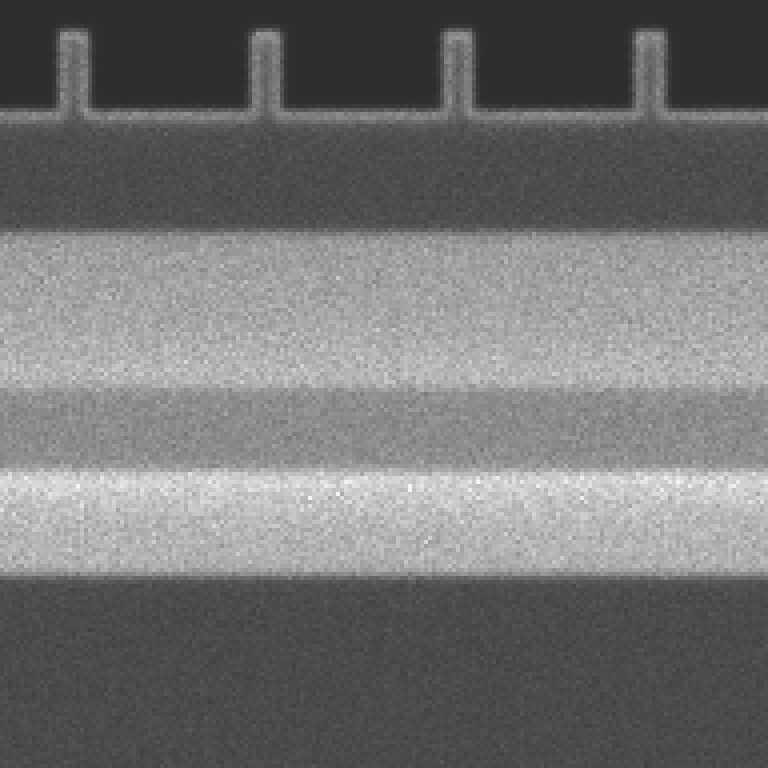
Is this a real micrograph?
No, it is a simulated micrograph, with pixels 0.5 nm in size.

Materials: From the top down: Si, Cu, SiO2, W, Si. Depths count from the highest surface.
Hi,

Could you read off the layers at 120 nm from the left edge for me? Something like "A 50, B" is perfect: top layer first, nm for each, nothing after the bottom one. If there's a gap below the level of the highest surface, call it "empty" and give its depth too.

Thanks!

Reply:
empty 40, Si 60, Cu 78, SiO2 42, W 52, Si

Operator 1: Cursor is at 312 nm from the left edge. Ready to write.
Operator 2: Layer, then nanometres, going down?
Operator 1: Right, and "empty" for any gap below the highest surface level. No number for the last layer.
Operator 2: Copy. empty 40, Si 60, Cu 78, SiO2 42, W 52, Si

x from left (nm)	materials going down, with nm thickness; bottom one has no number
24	empty 40, Si 60, Cu 78, SiO2 42, W 52, Si